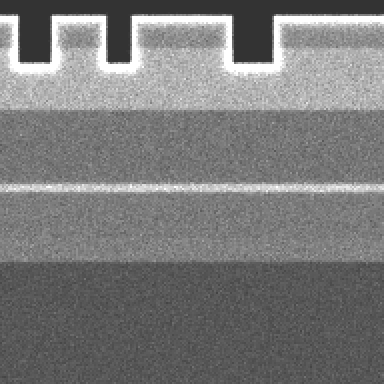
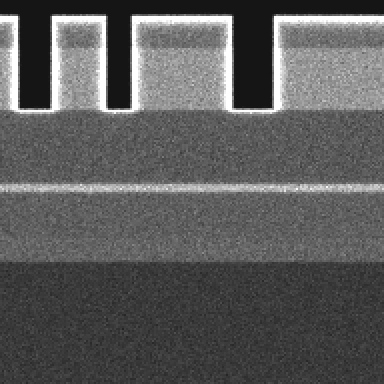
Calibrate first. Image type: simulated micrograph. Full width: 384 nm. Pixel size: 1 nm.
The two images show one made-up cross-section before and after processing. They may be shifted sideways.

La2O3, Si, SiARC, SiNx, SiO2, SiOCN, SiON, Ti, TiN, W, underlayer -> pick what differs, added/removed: SiO2 removed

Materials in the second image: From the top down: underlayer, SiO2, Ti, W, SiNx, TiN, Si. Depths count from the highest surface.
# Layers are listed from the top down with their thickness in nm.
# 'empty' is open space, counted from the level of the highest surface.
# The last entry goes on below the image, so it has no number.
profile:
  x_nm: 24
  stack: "empty 94, Ti 74, W 8, SiNx 46, TiN 24, Si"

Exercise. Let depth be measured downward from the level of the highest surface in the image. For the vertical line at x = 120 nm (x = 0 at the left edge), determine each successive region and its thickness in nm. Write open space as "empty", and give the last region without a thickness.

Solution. empty 94, Ti 74, W 8, SiNx 46, TiN 24, Si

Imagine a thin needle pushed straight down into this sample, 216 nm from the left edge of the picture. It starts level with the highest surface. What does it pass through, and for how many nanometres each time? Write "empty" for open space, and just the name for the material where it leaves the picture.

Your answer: underlayer 32, SiO2 62, Ti 74, W 8, SiNx 46, TiN 24, Si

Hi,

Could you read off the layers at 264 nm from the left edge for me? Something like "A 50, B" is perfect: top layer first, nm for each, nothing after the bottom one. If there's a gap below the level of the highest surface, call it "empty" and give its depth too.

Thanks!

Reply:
empty 94, Ti 74, W 8, SiNx 46, TiN 24, Si